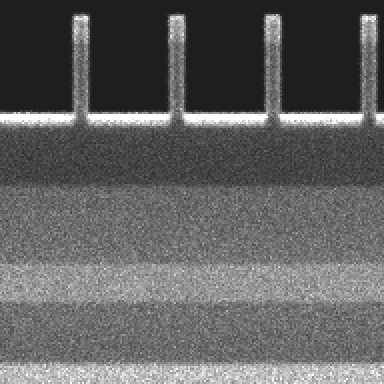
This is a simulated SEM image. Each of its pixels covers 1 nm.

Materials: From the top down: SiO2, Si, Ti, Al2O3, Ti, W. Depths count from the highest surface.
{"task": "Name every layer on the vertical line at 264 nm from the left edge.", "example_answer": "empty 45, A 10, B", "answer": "empty 98, SiO2 12, Si 60, Ti 78, Al2O3 38, Ti 62, W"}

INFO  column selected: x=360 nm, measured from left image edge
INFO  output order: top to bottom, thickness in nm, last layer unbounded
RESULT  empty 98, SiO2 12, Si 60, Ti 78, Al2O3 38, Ti 62, W